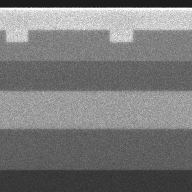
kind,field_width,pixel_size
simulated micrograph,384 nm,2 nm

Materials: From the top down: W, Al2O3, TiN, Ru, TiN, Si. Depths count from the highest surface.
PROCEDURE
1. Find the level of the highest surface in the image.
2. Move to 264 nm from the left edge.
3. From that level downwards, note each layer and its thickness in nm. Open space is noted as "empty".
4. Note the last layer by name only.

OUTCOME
W 68, Al2O3 38, TiN 60, Ru 76, TiN 82, Si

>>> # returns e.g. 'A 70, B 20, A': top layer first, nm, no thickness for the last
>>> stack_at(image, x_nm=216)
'W 44, Al2O3 62, TiN 60, Ru 76, TiN 82, Si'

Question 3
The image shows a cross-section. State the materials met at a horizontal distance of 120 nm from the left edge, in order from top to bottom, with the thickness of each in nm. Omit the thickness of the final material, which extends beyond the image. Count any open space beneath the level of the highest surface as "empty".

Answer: W 44, Al2O3 62, TiN 60, Ru 76, TiN 82, Si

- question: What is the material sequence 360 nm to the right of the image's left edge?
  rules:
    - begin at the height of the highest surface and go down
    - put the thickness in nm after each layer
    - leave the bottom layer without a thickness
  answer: W 44, Al2O3 62, TiN 60, Ru 76, TiN 82, Si